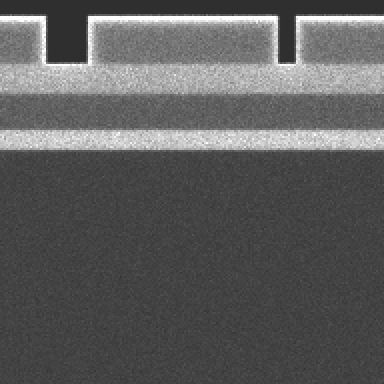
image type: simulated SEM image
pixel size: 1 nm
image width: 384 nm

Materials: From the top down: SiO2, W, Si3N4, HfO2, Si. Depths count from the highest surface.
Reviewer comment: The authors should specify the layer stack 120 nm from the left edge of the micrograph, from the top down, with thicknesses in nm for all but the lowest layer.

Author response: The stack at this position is SiO2 48, W 30, Si3N4 36, HfO2 20, Si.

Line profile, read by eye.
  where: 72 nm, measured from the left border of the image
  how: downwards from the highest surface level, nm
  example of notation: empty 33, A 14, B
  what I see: empty 48, W 30, Si3N4 36, HfO2 20, Si